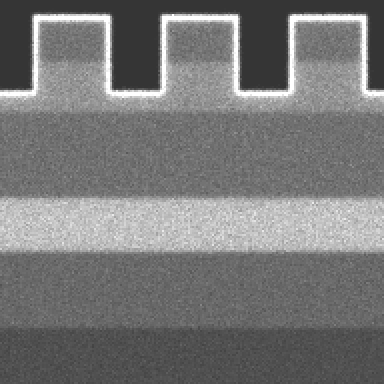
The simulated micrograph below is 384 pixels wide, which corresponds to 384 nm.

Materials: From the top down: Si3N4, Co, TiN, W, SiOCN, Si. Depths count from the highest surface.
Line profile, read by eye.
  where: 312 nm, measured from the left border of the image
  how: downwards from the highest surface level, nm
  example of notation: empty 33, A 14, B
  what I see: Si3N4 46, Co 50, TiN 86, W 54, SiOCN 76, Si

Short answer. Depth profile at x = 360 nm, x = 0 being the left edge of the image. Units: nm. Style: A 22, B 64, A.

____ Si3N4 46, Co 50, TiN 86, W 54, SiOCN 76, Si